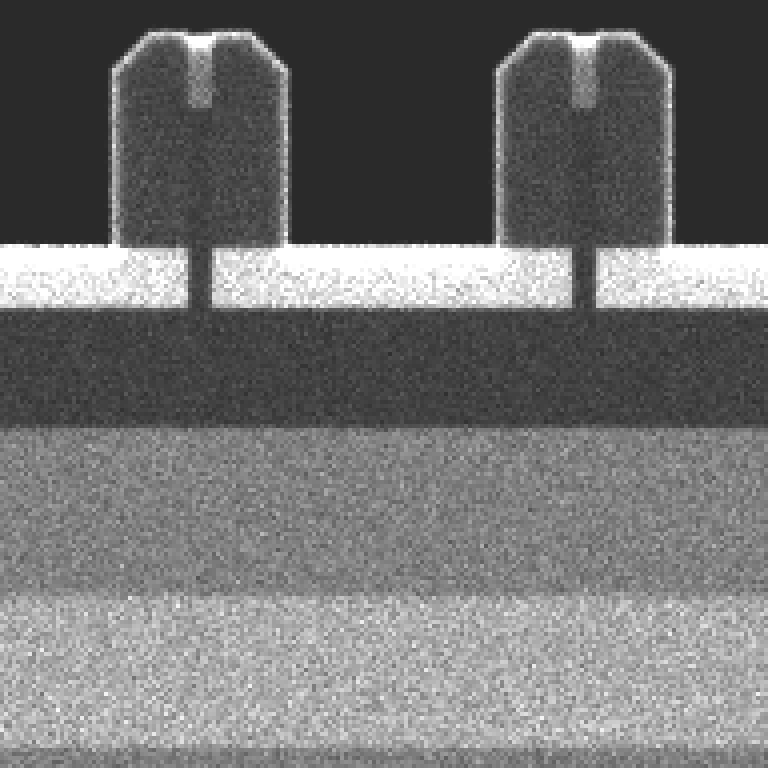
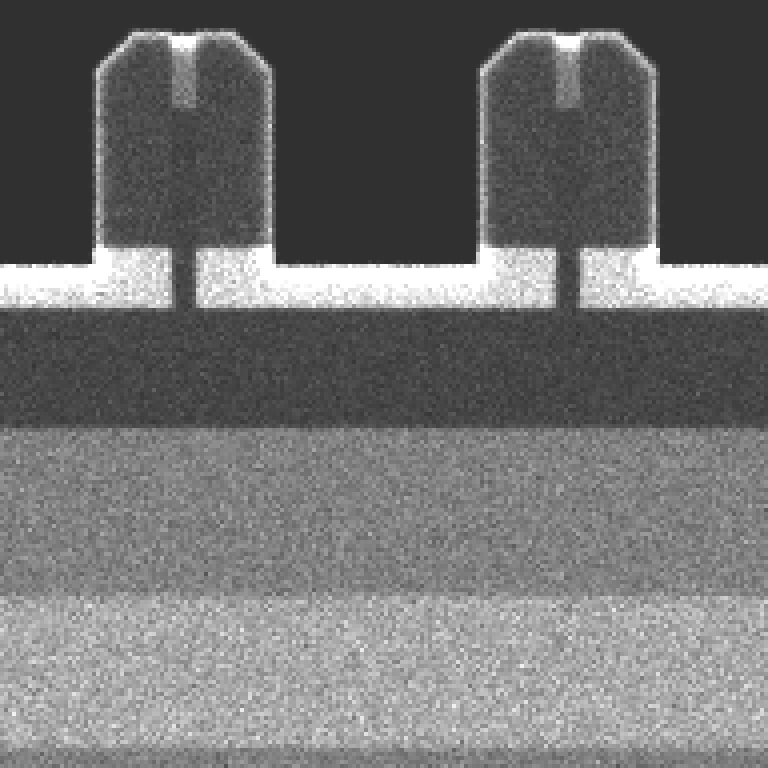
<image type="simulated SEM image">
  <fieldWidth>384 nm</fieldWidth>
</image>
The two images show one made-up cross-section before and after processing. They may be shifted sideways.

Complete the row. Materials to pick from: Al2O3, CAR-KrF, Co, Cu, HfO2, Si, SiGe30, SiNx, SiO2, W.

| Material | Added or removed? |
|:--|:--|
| HfO2 | removed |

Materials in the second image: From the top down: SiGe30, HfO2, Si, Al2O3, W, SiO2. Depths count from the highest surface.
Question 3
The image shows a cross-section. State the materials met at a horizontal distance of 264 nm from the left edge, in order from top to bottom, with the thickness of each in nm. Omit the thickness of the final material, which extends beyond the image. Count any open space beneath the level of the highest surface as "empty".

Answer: SiGe30 108, HfO2 30, Si 60, Al2O3 84, W 76, SiO2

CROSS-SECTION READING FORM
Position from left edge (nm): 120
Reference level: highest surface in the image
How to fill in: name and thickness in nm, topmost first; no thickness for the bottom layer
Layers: empty 4, SiGe30 104, HfO2 30, Si 60, Al2O3 84, W 76, SiO2